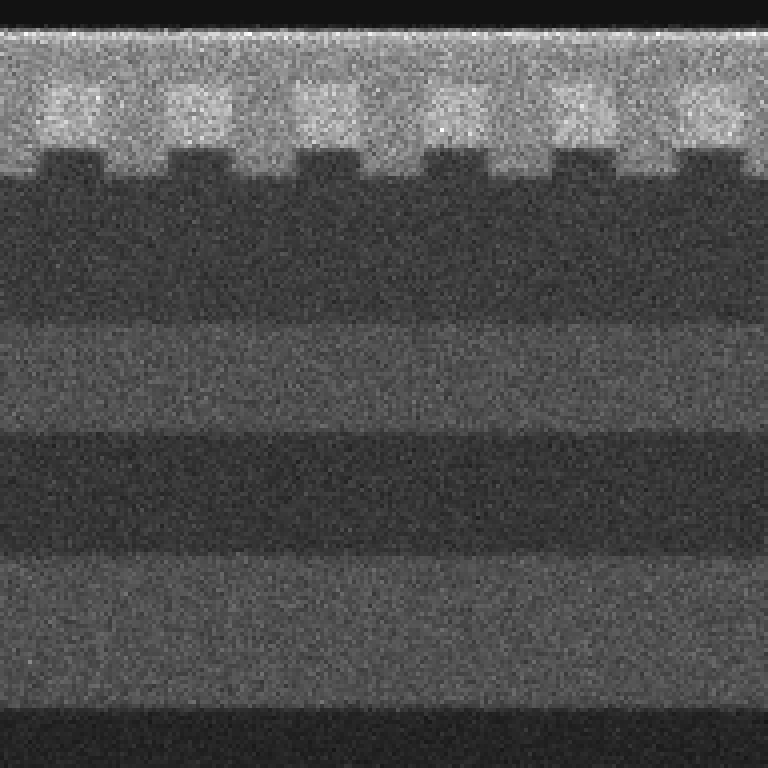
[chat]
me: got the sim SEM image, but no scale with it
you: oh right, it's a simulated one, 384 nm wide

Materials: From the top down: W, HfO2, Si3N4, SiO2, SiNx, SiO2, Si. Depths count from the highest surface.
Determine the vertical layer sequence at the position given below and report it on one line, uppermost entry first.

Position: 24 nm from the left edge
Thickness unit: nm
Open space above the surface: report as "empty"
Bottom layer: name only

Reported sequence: W 26, HfO2 32, Si3N4 88, SiO2 54, SiNx 62, SiO2 76, Si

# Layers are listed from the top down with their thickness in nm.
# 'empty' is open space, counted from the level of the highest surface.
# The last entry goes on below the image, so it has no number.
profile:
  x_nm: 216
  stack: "W 26, HfO2 32, Si3N4 88, SiO2 54, SiNx 62, SiO2 76, Si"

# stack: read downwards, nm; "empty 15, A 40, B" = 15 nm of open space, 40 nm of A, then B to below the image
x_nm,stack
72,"W 72, Si3N4 74, SiO2 54, SiNx 62, SiO2 76, Si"